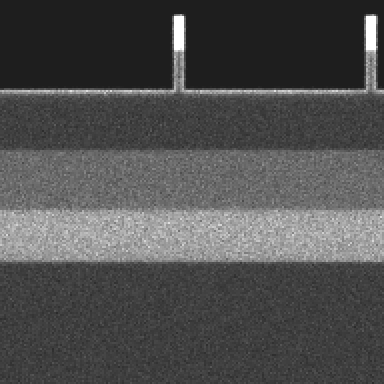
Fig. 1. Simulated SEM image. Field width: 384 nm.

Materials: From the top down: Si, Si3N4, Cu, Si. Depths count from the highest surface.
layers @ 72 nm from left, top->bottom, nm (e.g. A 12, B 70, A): empty 74, Si 60, Si3N4 60, Cu 52, Si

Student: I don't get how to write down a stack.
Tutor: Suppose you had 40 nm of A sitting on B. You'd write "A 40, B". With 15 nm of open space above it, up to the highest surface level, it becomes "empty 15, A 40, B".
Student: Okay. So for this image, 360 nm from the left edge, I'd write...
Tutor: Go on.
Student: empty 74, Si 60, Si3N4 60, Cu 52, Si